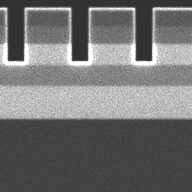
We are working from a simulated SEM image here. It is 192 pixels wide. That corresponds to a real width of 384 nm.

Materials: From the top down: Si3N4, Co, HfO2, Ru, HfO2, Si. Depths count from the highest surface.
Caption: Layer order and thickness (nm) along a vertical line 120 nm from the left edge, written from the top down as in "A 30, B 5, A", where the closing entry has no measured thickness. Si3N4 36, Co 36, HfO2 42, Ru 42, HfO2 66, Si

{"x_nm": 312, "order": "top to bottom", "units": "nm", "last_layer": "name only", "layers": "Si3N4 36, Co 36, HfO2 42, Ru 42, HfO2 66, Si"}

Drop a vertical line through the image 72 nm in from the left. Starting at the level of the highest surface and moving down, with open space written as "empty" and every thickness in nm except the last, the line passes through Si3N4 36, Co 36, HfO2 42, Ru 42, HfO2 66, Si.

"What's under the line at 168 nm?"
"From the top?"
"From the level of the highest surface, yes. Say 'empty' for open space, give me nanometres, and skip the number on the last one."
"empty 108, HfO2 6, Ru 42, HfO2 66, Si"